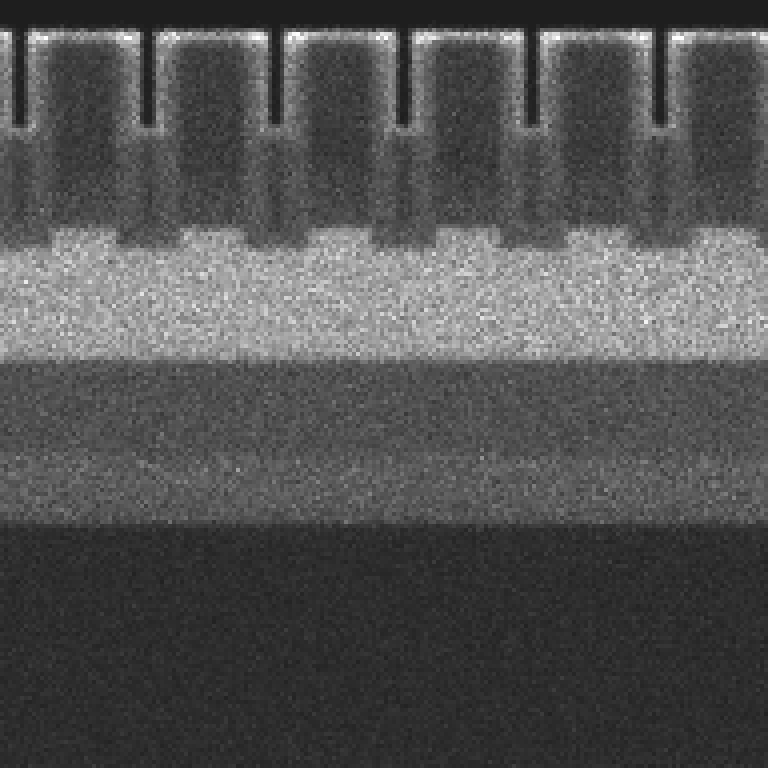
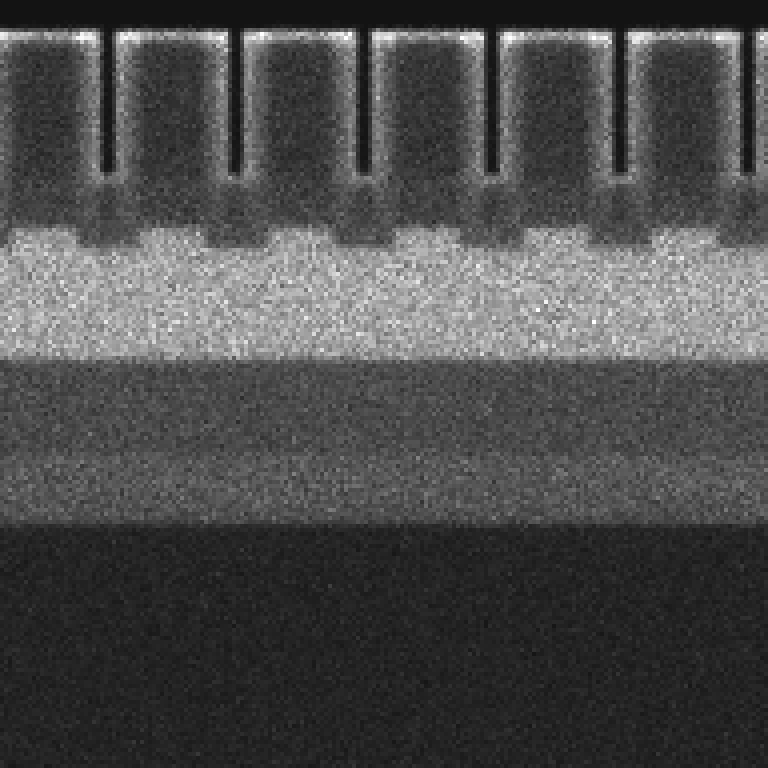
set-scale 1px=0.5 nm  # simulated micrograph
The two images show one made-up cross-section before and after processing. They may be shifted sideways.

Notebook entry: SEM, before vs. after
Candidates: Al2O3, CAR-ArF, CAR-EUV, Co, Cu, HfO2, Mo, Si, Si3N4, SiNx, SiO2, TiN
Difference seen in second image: Si3N4 removed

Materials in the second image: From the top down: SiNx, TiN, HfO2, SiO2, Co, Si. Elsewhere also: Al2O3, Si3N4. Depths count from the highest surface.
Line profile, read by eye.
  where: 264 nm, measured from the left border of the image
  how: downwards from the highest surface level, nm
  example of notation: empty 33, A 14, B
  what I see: SiNx 72, TiN 26, HfO2 66, SiO2 48, Co 34, Si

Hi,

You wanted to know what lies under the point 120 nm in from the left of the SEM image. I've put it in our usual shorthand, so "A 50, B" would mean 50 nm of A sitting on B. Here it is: empty 72, Si3N4 24, Al2O3 12, HfO2 56, SiO2 48, Co 34, Si